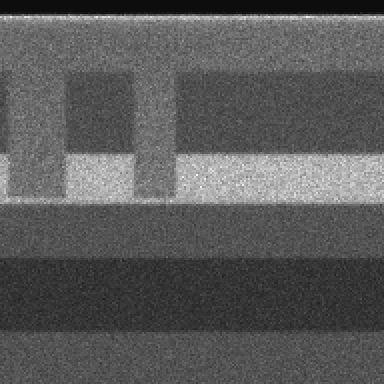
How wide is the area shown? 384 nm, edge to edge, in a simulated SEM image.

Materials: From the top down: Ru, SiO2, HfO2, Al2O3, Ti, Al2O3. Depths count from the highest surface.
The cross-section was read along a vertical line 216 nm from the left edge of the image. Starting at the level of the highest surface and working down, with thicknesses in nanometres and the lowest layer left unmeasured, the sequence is Ru 56, SiO2 82, HfO2 50, Al2O3 54, Ti 74, Al2O3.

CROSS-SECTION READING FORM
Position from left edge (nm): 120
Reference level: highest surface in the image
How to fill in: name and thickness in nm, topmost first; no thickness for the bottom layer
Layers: Ru 56, SiO2 82, HfO2 50, Al2O3 54, Ti 74, Al2O3